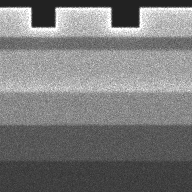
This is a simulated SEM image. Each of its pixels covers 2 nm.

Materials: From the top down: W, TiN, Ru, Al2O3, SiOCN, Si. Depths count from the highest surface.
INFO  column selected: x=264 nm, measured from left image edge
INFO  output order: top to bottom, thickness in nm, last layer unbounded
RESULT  empty 40, W 18, TiN 26, Ru 84, Al2O3 66, SiOCN 72, Si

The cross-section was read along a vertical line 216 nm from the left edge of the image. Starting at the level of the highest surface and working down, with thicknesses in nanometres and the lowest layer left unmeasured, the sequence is W 58, TiN 26, Ru 84, Al2O3 66, SiOCN 72, Si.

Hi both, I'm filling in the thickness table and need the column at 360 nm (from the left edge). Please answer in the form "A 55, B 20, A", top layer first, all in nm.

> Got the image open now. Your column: W 58, TiN 26, Ru 84, Al2O3 66, SiOCN 72, Si